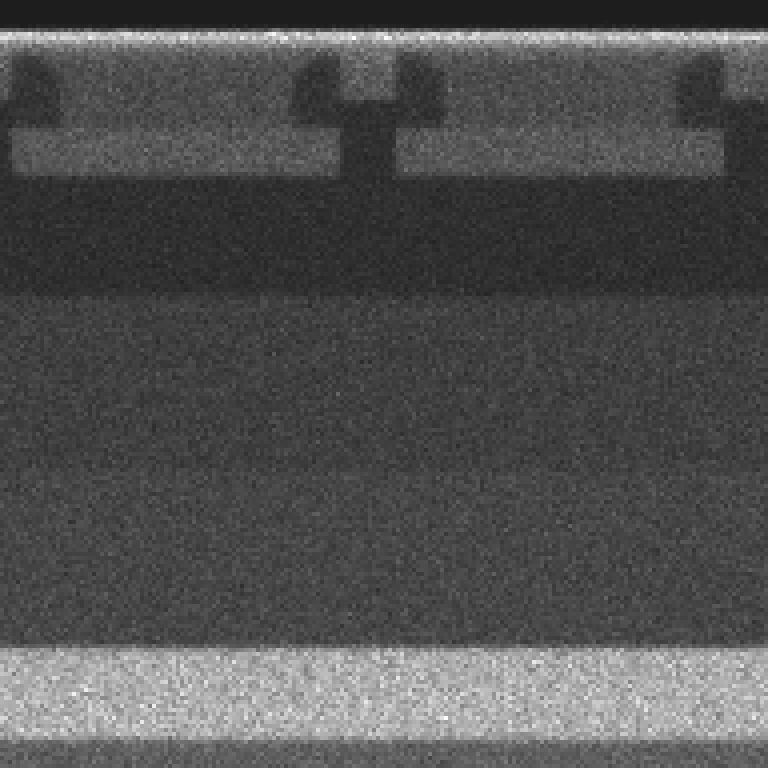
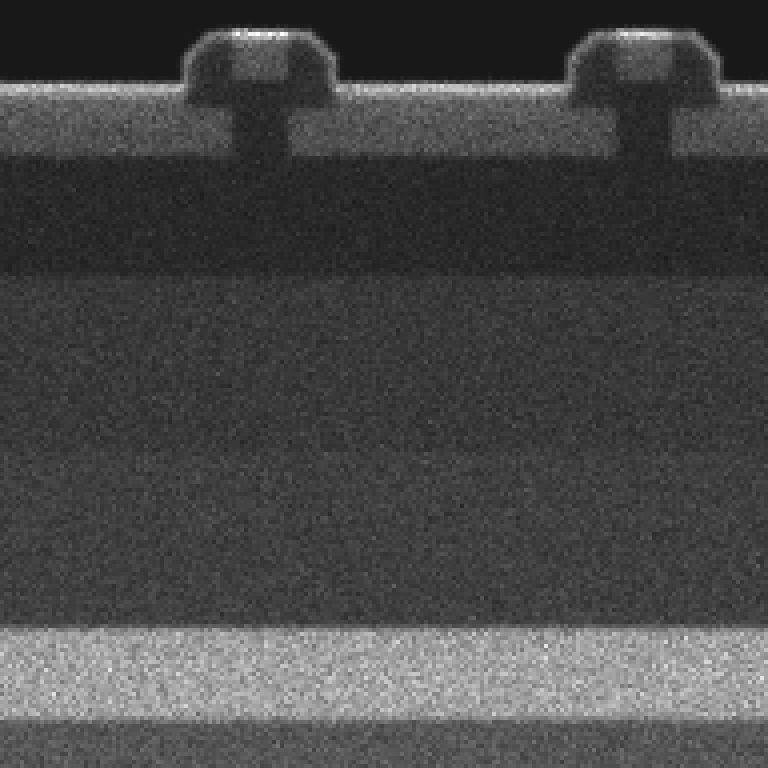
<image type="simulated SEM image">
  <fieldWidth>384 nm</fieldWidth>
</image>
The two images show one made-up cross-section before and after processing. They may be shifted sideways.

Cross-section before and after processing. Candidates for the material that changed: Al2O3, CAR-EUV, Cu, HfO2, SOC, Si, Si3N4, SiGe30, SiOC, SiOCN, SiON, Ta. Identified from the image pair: SOC (removed).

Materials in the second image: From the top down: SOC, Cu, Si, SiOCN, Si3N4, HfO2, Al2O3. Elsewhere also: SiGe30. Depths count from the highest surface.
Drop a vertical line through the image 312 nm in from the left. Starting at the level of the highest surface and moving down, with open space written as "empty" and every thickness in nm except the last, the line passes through Cu 24, Si 98, SiOCN 88, Si3N4 88, HfO2 46, Al2O3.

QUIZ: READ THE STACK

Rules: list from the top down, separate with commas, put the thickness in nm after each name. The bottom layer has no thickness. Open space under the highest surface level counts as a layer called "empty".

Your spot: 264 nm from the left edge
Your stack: empty 26, SOC 12, Cu 24, Si 60, SiOCN 88, Si3N4 88, HfO2 46, Al2O3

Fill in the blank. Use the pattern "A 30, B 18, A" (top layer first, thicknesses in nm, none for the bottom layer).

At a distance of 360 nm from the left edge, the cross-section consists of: empty 26, SOC 12, Cu 24, Si 60, SiOCN 88, Si3N4 88, HfO2 46, Al2O3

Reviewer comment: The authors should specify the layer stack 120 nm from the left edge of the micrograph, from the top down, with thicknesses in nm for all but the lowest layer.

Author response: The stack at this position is Cu 24, Si 98, SiOCN 88, Si3N4 88, HfO2 46, Al2O3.